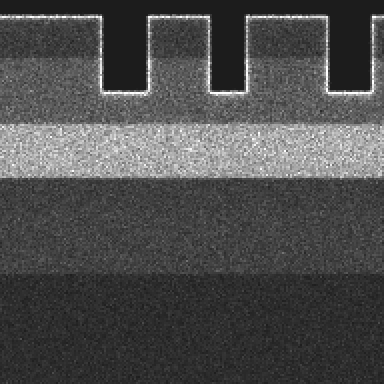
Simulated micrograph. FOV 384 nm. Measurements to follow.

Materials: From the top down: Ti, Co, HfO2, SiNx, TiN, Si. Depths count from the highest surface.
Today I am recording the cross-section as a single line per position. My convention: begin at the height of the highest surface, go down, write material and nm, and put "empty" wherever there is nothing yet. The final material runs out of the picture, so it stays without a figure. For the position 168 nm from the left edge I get Ti 42, Co 66, HfO2 54, SiNx 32, TiN 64, Si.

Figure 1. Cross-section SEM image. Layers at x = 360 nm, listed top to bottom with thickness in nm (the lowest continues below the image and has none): empty 76, Co 32, HfO2 54, SiNx 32, TiN 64, Si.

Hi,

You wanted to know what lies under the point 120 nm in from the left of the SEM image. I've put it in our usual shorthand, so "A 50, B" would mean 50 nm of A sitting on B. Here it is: empty 76, Co 32, HfO2 54, SiNx 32, TiN 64, Si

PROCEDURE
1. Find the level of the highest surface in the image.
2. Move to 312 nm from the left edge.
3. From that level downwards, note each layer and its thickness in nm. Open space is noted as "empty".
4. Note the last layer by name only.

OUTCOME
Ti 42, Co 66, HfO2 54, SiNx 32, TiN 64, Si